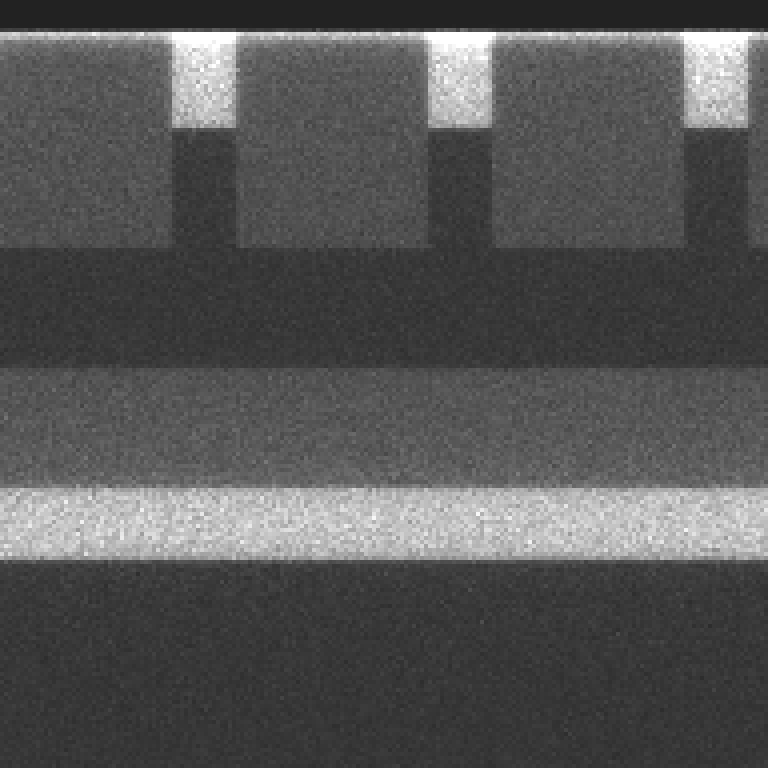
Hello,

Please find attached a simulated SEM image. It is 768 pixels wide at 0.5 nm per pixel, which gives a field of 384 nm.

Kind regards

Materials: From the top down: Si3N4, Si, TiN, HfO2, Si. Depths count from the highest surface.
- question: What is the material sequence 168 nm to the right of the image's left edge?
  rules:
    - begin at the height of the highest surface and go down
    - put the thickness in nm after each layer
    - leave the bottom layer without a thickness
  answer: Si3N4 108, Si 60, TiN 60, HfO2 36, Si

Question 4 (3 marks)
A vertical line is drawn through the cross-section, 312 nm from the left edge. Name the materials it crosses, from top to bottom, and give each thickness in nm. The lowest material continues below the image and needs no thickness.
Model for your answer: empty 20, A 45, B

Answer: Si3N4 108, Si 60, TiN 60, HfO2 36, Si